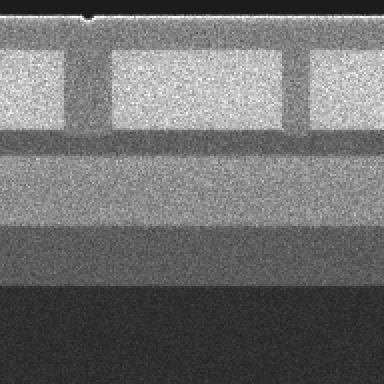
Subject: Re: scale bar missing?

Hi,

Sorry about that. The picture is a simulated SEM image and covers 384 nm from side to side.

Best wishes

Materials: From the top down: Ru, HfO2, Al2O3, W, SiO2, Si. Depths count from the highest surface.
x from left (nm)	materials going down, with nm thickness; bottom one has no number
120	Ru 34, HfO2 80, Al2O3 26, W 70, SiO2 60, Si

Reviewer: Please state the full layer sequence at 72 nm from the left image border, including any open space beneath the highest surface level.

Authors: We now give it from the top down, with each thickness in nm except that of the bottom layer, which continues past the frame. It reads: Ru 120, Al2O3 20, W 70, SiO2 60, Si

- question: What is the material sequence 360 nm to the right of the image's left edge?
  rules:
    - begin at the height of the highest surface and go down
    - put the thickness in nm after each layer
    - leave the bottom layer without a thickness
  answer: Ru 34, HfO2 80, Al2O3 26, W 70, SiO2 60, Si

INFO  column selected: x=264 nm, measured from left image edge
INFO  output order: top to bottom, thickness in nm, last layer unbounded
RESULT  Ru 34, HfO2 80, Al2O3 26, W 70, SiO2 60, Si